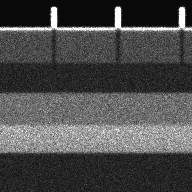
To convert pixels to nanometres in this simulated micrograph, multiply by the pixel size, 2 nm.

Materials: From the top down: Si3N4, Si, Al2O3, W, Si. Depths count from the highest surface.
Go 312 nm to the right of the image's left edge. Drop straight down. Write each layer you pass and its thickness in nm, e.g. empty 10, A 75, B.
empty 40, Si3N4 70, Si 60, Al2O3 64, W 56, Si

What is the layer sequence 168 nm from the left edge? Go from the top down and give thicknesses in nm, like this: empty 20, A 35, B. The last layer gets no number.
empty 40, Si3N4 70, Si 60, Al2O3 64, W 56, Si